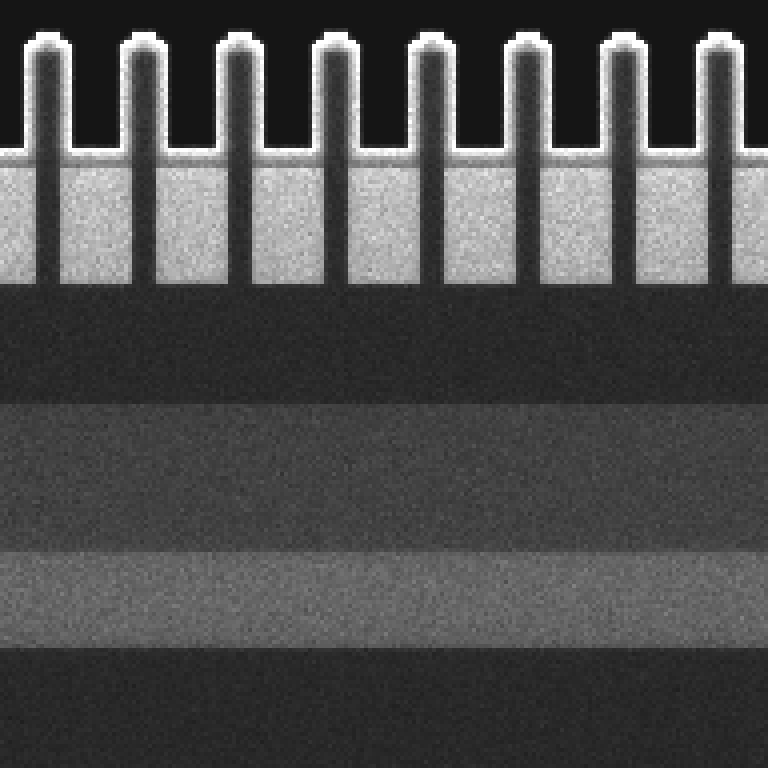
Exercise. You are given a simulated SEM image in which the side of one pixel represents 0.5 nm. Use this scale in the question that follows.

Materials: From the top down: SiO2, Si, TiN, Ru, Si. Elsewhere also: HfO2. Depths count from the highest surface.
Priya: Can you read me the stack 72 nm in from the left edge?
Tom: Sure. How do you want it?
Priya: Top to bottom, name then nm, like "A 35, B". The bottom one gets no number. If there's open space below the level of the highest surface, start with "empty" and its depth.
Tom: SiO2 10, Si 176, TiN 74, Ru 48, Si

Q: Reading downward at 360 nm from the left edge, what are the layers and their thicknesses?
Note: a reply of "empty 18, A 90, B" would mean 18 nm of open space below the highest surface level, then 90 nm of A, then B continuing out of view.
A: SiO2 10, Si 176, TiN 74, Ru 48, Si